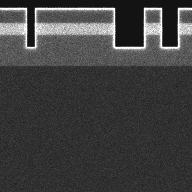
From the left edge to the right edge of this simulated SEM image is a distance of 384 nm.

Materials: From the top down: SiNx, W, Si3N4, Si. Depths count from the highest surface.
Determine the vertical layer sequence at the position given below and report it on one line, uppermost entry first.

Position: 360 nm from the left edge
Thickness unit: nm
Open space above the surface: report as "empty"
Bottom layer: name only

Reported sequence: SiNx 30, W 24, Si3N4 62, Si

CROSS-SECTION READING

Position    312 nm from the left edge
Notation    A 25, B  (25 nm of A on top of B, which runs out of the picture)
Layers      SiNx 30, W 24, Si3N4 62, Si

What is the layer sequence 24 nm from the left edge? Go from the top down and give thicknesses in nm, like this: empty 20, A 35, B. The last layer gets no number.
SiNx 30, W 24, Si3N4 62, Si